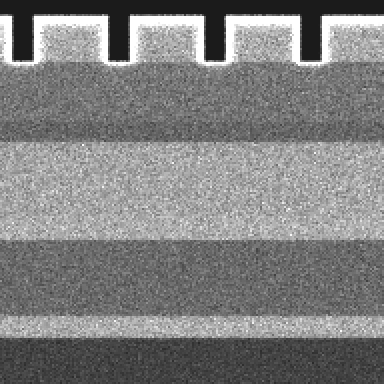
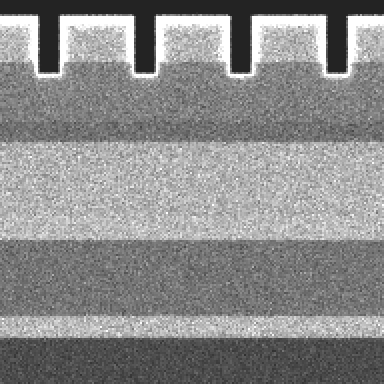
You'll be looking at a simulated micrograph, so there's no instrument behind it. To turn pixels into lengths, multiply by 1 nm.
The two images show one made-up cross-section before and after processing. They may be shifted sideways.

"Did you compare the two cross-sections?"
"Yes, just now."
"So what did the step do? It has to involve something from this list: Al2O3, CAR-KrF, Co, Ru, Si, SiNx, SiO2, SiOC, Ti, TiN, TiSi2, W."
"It removed TiN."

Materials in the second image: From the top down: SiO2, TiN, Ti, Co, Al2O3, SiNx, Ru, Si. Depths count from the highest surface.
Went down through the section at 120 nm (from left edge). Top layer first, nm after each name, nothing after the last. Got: SiO2 46, TiN 60, Ti 20, Co 74, Al2O3 24, SiNx 76, Ru 22, Si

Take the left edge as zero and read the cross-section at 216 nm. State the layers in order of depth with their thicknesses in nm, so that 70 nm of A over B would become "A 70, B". SiO2 46, TiN 60, Ti 20, Co 74, Al2O3 24, SiNx 76, Ru 22, Si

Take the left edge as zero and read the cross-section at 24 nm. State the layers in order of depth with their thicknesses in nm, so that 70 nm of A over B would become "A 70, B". SiO2 46, TiN 60, Ti 20, Co 74, Al2O3 24, SiNx 76, Ru 22, Si